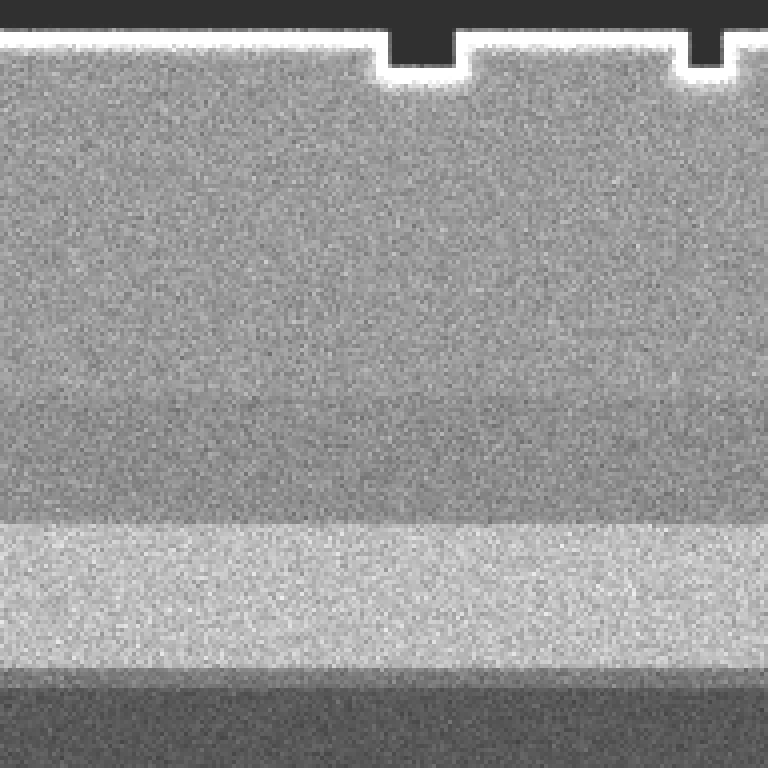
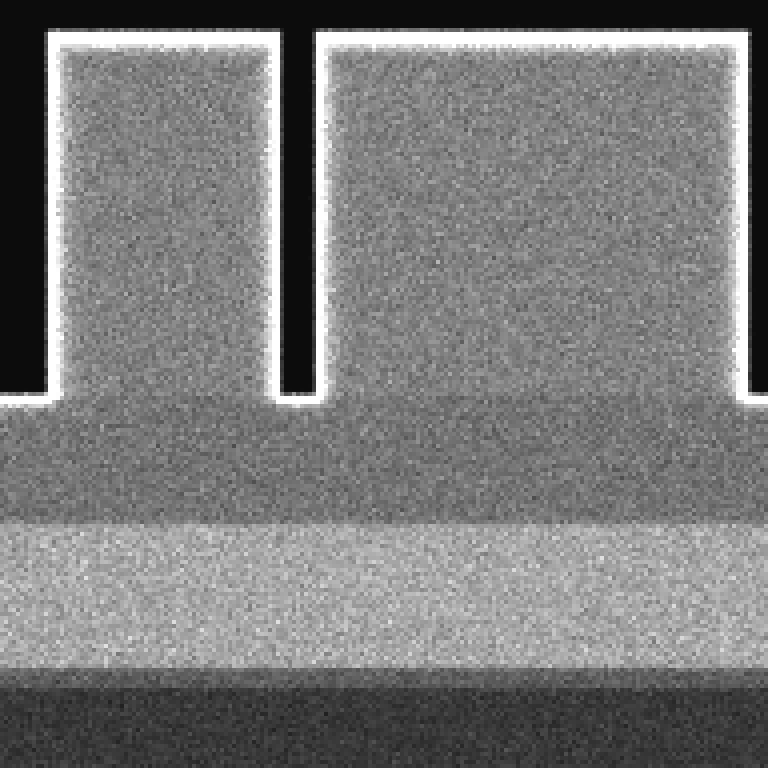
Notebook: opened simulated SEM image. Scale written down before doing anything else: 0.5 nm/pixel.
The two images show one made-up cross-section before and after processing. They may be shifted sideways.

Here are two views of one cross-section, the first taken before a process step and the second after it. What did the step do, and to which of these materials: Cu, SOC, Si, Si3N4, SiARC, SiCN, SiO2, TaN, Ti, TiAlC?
It removed SOC.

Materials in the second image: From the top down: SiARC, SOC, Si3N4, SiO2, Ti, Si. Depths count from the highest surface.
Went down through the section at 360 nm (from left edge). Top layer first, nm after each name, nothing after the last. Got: SiARC 18, SOC 164, Si3N4 64, SiO2 72, Ti 10, Si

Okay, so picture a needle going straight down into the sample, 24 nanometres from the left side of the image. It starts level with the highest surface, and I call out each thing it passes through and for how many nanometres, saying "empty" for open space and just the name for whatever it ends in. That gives SiARC 18, SOC 164, Si3N4 64, SiO2 72, Ti 10, Si